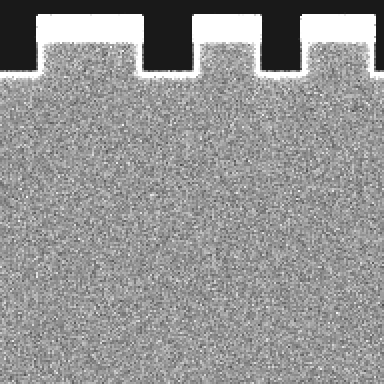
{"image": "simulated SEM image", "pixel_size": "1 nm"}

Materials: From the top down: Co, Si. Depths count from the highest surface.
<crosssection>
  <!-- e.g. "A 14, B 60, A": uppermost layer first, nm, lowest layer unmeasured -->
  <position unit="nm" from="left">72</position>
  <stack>Co 26, Si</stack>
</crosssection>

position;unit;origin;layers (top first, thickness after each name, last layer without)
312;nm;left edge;Co 26, Si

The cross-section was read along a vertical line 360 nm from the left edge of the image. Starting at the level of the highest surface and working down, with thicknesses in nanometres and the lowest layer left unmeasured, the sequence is Co 26, Si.